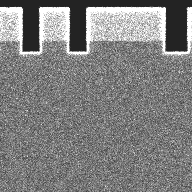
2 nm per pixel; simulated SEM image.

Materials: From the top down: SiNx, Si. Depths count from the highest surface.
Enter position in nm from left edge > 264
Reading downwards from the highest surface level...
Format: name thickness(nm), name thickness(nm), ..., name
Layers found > SiNx 66, Si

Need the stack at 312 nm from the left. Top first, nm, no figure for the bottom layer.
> SiNx 66, Si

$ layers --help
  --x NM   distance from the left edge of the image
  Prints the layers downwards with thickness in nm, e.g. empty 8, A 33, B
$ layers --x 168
empty 88, Si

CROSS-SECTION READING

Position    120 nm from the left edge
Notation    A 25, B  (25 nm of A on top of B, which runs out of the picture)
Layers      SiNx 66, Si